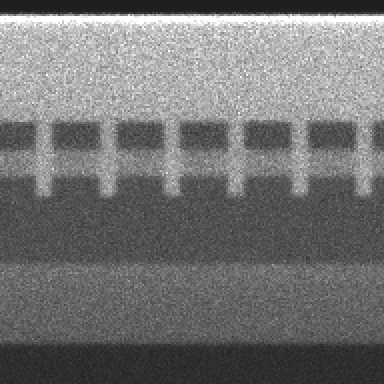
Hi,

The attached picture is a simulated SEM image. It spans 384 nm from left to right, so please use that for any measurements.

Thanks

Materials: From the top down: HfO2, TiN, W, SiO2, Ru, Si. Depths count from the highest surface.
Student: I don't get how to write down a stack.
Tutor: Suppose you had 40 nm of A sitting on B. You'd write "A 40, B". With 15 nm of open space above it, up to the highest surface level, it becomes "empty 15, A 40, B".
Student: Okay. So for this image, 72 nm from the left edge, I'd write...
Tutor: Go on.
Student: HfO2 106, TiN 28, W 26, SiO2 88, Ru 80, Si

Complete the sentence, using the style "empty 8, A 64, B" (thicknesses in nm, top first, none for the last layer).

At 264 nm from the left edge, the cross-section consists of HfO2 106, TiN 28, W 26, SiO2 88, Ru 80, Si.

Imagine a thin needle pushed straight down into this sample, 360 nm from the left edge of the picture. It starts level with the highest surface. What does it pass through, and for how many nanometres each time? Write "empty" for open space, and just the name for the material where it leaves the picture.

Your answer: HfO2 180, SiO2 68, Ru 80, Si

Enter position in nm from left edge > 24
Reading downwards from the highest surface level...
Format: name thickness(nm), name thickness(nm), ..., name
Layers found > HfO2 106, TiN 28, W 26, SiO2 88, Ru 80, Si